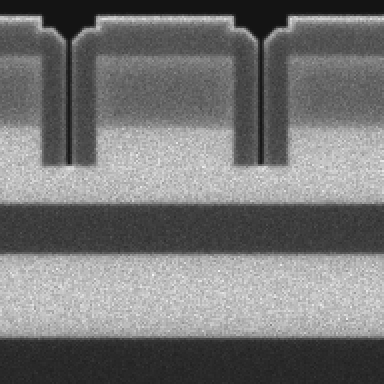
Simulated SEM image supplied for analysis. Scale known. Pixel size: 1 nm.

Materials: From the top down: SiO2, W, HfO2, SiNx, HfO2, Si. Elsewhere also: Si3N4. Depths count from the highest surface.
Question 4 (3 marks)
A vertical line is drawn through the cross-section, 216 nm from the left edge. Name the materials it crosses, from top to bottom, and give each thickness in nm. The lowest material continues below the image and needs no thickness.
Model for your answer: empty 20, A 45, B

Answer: SiO2 40, W 72, HfO2 76, SiNx 50, HfO2 84, Si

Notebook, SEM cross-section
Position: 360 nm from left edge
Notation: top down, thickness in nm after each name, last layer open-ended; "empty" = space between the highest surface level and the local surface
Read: SiO2 40, W 72, HfO2 76, SiNx 50, HfO2 84, Si